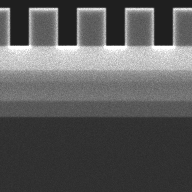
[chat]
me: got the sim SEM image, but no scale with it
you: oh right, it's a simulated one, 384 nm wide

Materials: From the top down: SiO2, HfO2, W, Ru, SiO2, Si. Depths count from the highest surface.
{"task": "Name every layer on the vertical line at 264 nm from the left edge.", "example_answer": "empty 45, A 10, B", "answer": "SiO2 76, HfO2 48, W 24, Ru 38, SiO2 32, Si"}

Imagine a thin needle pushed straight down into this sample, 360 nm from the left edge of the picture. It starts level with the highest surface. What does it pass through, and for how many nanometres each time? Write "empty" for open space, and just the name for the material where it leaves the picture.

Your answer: SiO2 76, HfO2 48, W 24, Ru 38, SiO2 32, Si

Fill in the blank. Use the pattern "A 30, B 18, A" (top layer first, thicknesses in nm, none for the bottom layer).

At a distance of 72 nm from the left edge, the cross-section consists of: SiO2 76, HfO2 48, W 24, Ru 38, SiO2 32, Si